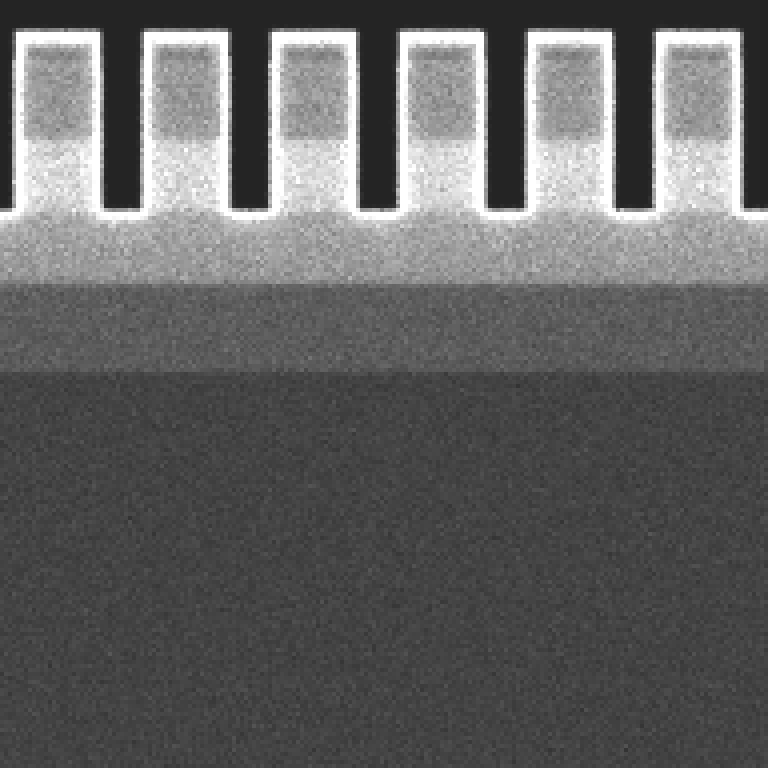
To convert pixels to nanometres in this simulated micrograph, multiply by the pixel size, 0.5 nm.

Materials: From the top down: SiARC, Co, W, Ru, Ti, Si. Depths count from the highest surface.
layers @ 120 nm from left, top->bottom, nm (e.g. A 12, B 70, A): empty 90, Ru 36, Ti 44, Si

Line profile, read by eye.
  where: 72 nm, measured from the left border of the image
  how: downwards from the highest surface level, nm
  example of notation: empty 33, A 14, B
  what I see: SiARC 14, Co 40, W 36, Ru 36, Ti 44, Si